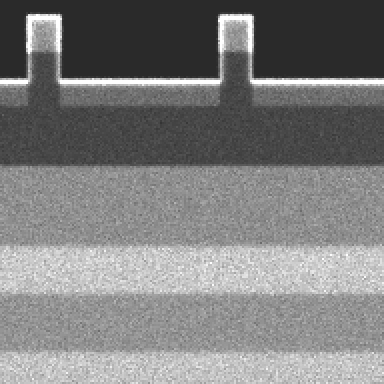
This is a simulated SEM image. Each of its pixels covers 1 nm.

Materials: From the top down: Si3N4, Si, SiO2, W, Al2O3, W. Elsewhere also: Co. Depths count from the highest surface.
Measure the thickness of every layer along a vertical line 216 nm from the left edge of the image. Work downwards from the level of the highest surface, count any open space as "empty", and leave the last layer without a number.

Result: empty 64, Si3N4 26, Si 60, SiO2 80, W 48, Al2O3 58, W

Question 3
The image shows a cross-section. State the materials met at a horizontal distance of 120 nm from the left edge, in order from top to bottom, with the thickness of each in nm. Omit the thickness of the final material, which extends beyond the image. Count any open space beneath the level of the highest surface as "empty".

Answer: empty 64, Si3N4 26, Si 60, SiO2 80, W 48, Al2O3 58, W